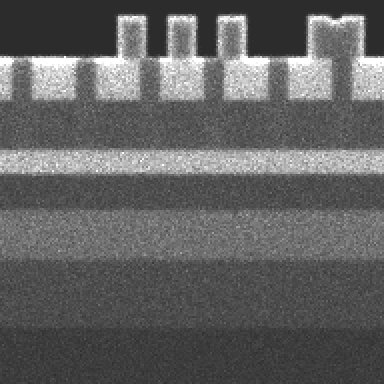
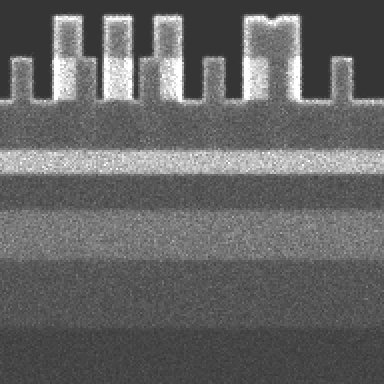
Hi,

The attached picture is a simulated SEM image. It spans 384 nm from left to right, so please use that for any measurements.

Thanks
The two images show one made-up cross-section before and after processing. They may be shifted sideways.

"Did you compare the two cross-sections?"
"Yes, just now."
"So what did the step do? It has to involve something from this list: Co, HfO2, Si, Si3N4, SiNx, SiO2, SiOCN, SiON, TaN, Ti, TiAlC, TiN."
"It removed HfO2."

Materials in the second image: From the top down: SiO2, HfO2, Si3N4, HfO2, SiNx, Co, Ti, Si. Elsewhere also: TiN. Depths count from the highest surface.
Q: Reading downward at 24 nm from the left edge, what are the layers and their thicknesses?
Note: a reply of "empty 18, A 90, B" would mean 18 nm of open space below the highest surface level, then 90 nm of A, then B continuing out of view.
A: empty 42, TiN 92, HfO2 24, SiNx 36, Co 50, Ti 68, Si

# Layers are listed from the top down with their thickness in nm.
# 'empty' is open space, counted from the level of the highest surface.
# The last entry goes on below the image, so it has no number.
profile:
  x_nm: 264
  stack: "SiO2 42, HfO2 42, Si3N4 50, HfO2 24, SiNx 36, Co 50, Ti 68, Si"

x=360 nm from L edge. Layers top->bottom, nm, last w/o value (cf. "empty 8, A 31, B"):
empty 84, Si3N4 50, HfO2 24, SiNx 36, Co 50, Ti 68, Si